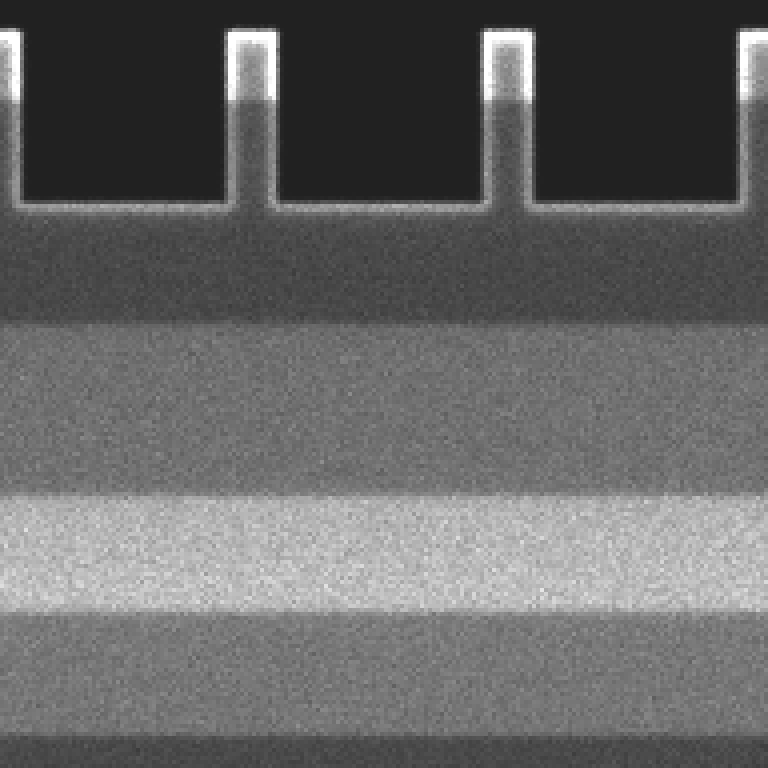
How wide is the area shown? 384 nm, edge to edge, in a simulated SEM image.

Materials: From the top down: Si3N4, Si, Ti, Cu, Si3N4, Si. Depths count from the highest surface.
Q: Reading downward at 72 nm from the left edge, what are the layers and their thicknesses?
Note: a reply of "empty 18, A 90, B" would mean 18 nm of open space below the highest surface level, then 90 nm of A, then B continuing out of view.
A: empty 86, Si 60, Ti 86, Cu 58, Si3N4 62, Si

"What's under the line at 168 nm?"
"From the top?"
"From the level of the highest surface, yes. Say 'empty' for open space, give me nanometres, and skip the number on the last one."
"empty 86, Si 60, Ti 86, Cu 58, Si3N4 62, Si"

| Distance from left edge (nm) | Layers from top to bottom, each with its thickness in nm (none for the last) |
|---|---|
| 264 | Si3N4 34, Si 112, Ti 86, Cu 58, Si3N4 62, Si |